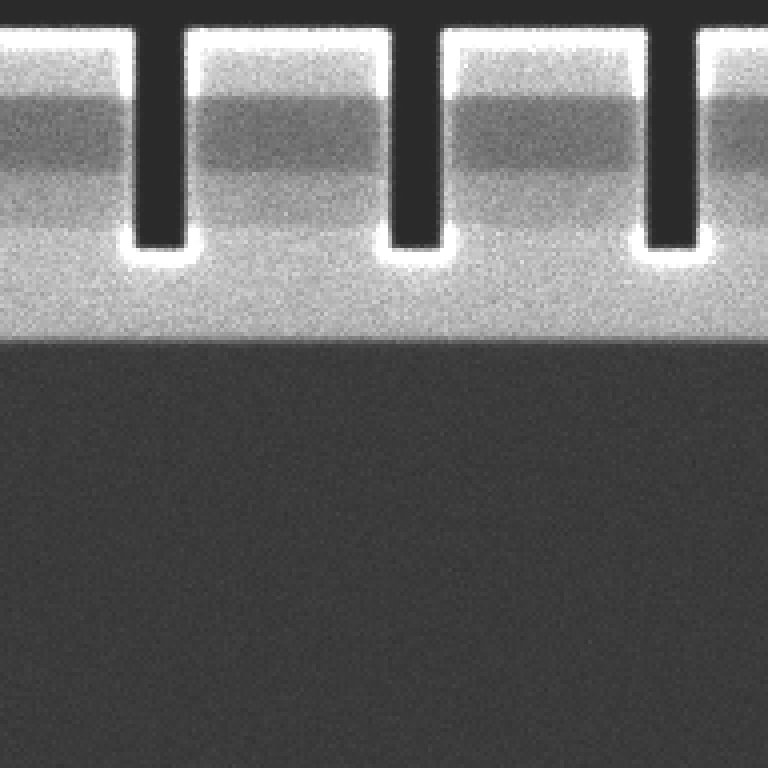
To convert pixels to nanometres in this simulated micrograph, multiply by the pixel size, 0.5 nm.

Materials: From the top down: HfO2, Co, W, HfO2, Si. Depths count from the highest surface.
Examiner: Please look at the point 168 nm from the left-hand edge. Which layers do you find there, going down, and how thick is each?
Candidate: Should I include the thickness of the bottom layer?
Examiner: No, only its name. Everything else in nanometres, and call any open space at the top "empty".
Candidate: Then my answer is HfO2 32, Co 38, W 28, HfO2 56, Si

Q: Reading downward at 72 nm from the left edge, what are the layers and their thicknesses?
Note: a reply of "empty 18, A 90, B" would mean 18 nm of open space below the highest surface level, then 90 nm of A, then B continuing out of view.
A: empty 110, HfO2 44, Si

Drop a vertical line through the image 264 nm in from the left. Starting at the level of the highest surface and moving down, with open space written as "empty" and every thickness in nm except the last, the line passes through HfO2 32, Co 38, W 28, HfO2 56, Si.